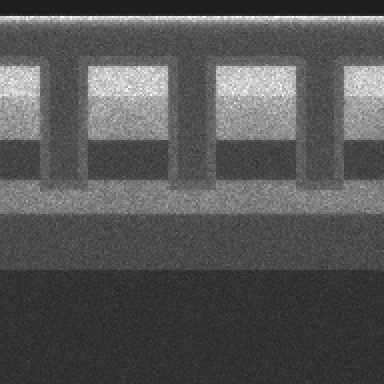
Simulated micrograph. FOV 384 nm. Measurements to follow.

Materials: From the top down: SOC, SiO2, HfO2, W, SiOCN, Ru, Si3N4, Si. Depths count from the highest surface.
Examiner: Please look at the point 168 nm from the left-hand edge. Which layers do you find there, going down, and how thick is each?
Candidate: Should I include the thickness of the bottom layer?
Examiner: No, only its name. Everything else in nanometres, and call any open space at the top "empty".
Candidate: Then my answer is SOC 40, SiO2 134, Ru 24, Si3N4 56, Si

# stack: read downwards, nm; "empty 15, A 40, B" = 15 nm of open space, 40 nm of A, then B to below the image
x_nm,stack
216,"SOC 40, SiO2 10, HfO2 30, W 44, SiOCN 40, Ru 34, Si3N4 56, Si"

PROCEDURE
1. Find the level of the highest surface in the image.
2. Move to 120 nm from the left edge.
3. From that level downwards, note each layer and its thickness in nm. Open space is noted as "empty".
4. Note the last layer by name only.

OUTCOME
SOC 40, SiO2 10, HfO2 30, W 44, SiOCN 40, Ru 34, Si3N4 56, Si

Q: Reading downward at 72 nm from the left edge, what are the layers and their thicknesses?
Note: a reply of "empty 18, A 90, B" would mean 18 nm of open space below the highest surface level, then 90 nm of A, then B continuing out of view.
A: SOC 164, SiO2 10, Ru 24, Si3N4 56, Si